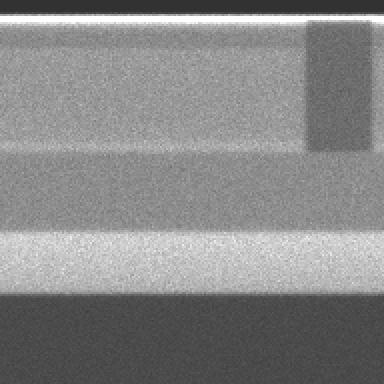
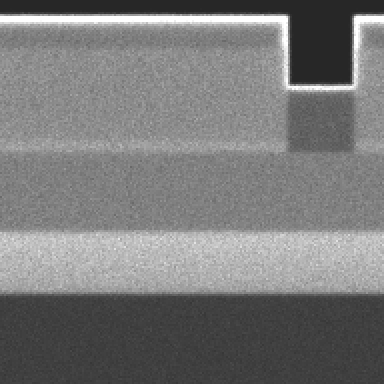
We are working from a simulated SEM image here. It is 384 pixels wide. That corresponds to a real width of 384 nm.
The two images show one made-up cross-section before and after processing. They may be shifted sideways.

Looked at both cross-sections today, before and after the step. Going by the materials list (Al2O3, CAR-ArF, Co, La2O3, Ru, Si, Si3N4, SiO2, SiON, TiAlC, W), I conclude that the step removed Si3N4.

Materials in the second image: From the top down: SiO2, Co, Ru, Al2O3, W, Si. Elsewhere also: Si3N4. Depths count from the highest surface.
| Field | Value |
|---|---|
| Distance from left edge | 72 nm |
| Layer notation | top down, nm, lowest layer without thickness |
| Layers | SiO2 32, Co 94, Ru 10, Al2O3 80, W 62, Si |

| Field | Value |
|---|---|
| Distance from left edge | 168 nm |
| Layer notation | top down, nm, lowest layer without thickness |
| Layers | SiO2 32, Co 94, Ru 10, Al2O3 80, W 62, Si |